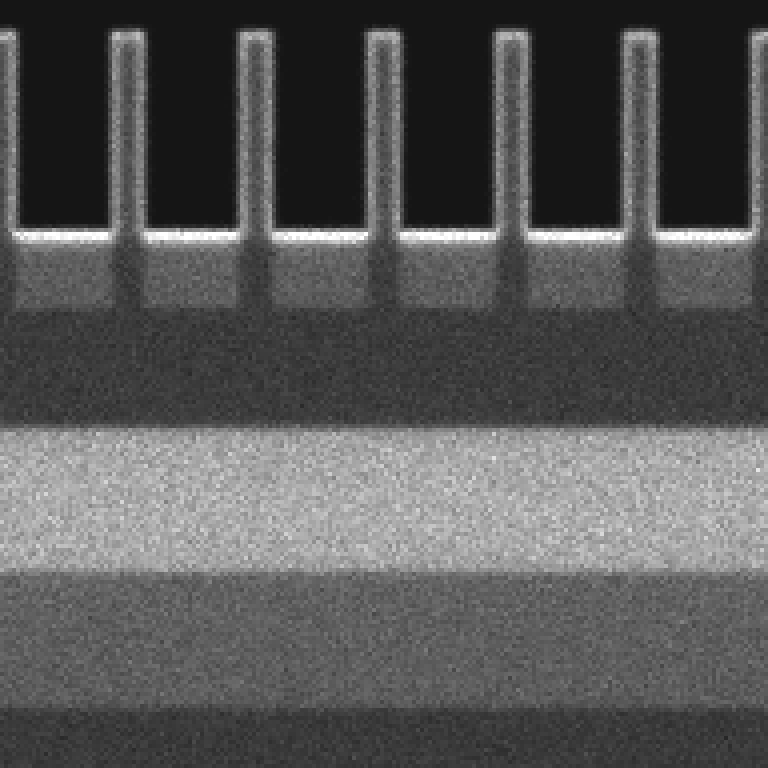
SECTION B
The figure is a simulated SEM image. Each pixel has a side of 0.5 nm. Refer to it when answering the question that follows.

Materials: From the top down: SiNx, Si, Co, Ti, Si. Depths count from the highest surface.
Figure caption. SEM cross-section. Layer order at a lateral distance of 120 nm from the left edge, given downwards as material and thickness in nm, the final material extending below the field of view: Si 198, Co 72, Ti 68, Si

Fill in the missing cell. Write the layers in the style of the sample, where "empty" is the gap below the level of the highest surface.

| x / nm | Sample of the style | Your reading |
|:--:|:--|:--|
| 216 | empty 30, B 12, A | empty 100, SiNx 38, Si 60, Co 72, Ti 68, Si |